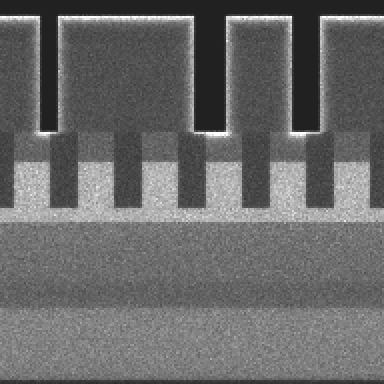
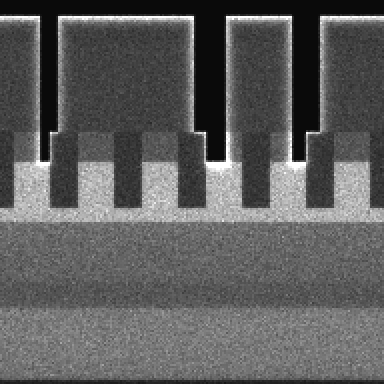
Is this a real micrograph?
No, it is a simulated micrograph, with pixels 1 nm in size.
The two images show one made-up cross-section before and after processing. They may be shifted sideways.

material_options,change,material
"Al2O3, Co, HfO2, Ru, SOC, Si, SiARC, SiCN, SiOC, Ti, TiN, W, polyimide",removed,Al2O3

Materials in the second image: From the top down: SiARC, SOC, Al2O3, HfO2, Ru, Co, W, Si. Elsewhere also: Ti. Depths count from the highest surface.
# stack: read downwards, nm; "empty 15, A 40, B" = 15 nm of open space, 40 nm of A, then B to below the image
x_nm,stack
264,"SiARC 26, SOC 90, Ti 76, HfO2 14, Ru 60, Co 26, W 72, Si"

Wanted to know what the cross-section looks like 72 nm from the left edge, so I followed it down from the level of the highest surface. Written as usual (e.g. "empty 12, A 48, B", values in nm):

SiARC 26, SOC 90, Ti 76, HfO2 14, Ru 60, Co 26, W 72, Si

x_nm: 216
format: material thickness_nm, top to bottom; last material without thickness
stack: empty 146, HfO2 60, Ru 60, Co 26, W 72, Si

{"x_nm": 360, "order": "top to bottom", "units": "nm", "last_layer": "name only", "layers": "SiARC 26, SOC 90, Al2O3 30, HfO2 60, Ru 60, Co 26, W 72, Si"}